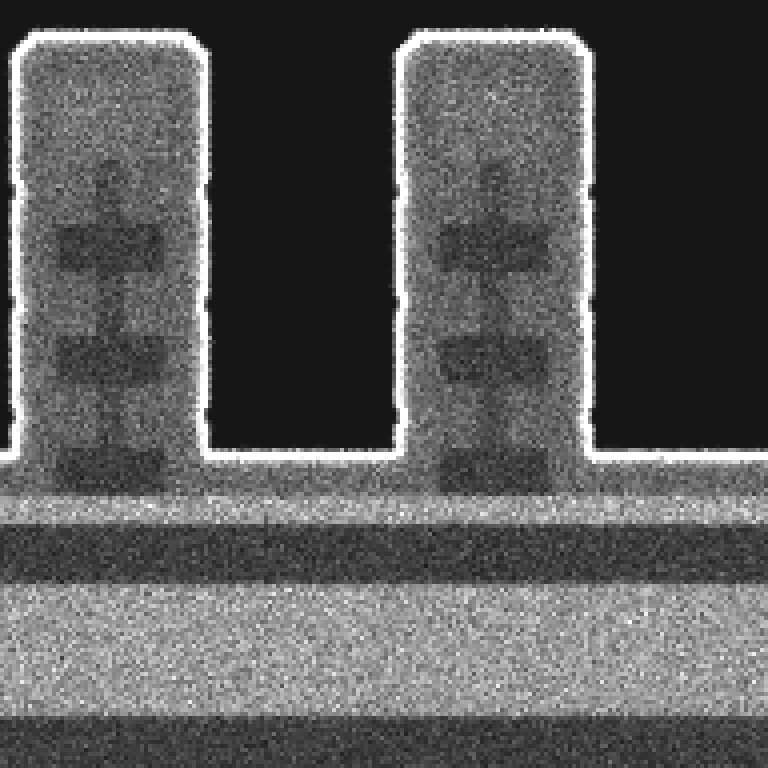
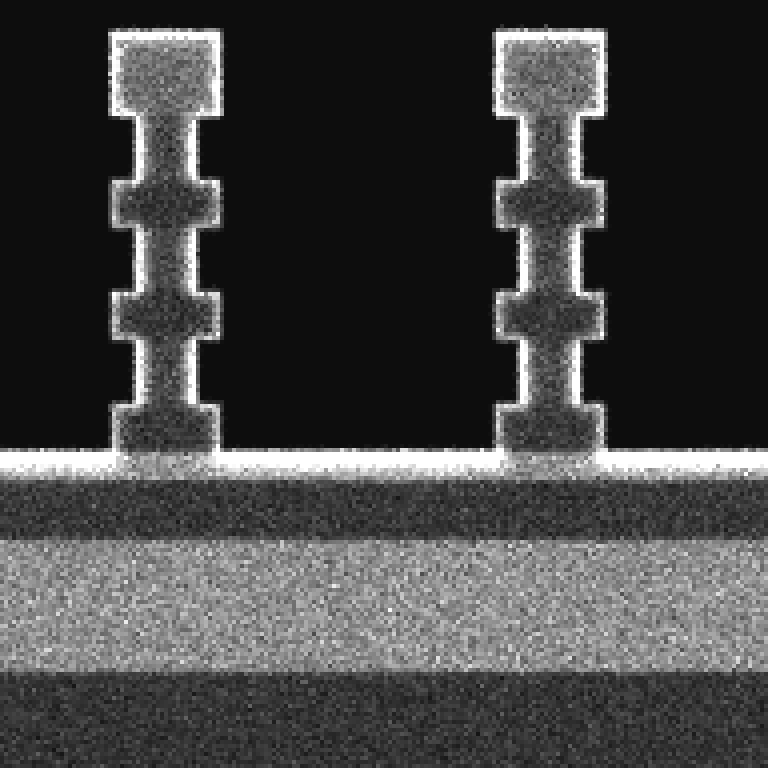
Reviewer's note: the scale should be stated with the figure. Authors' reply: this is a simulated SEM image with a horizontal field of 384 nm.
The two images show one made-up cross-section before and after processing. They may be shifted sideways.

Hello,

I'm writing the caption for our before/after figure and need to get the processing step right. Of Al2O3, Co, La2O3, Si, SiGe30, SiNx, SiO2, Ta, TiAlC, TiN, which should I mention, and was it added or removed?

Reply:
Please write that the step removed SiNx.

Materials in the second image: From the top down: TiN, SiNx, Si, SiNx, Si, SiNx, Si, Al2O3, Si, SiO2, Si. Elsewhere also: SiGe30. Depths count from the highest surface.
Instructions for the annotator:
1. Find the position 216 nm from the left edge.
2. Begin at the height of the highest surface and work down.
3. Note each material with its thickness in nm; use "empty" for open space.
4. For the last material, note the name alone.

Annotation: empty 210, Al2O3 14, Si 30, SiO2 66, Si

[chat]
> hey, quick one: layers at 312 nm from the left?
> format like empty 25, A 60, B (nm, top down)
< empty 210, Al2O3 14, Si 30, SiO2 66, Si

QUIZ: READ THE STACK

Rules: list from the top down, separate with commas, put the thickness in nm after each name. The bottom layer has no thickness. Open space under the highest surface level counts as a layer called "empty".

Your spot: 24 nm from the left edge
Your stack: empty 210, Al2O3 14, Si 30, SiO2 66, Si